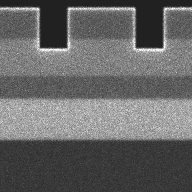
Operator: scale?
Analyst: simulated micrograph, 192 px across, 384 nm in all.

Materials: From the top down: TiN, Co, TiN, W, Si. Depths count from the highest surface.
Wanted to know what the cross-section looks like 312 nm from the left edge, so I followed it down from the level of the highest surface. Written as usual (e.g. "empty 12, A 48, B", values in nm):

empty 82, Co 54, TiN 46, W 82, Si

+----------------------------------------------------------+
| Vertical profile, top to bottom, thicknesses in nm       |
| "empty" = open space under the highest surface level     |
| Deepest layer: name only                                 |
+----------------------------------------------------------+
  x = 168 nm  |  TiN 62, Co 74, TiN 46, W 82, Si